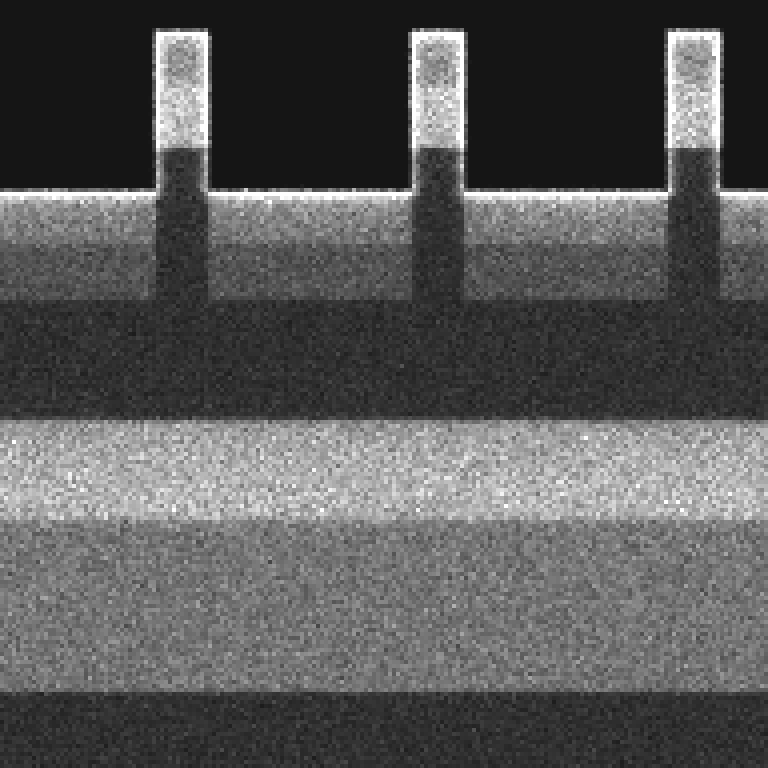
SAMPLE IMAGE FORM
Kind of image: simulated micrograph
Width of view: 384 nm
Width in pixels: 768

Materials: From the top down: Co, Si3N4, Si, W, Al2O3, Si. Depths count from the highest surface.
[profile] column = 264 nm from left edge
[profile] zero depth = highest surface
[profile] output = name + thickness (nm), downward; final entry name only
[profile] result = empty 80, Co 26, Si3N4 28, Si 60, W 50, Al2O3 86, Si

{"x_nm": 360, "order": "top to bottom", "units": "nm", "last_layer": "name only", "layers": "empty 80, Co 26, Si3N4 28, Si 60, W 50, Al2O3 86, Si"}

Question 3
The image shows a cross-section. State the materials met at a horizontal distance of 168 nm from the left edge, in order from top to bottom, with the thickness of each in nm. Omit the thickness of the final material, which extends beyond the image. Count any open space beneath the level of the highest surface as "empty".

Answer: empty 80, Co 26, Si3N4 28, Si 60, W 50, Al2O3 86, Si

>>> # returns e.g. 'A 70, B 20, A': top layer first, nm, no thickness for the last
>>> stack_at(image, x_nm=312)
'empty 80, Co 26, Si3N4 28, Si 60, W 50, Al2O3 86, Si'